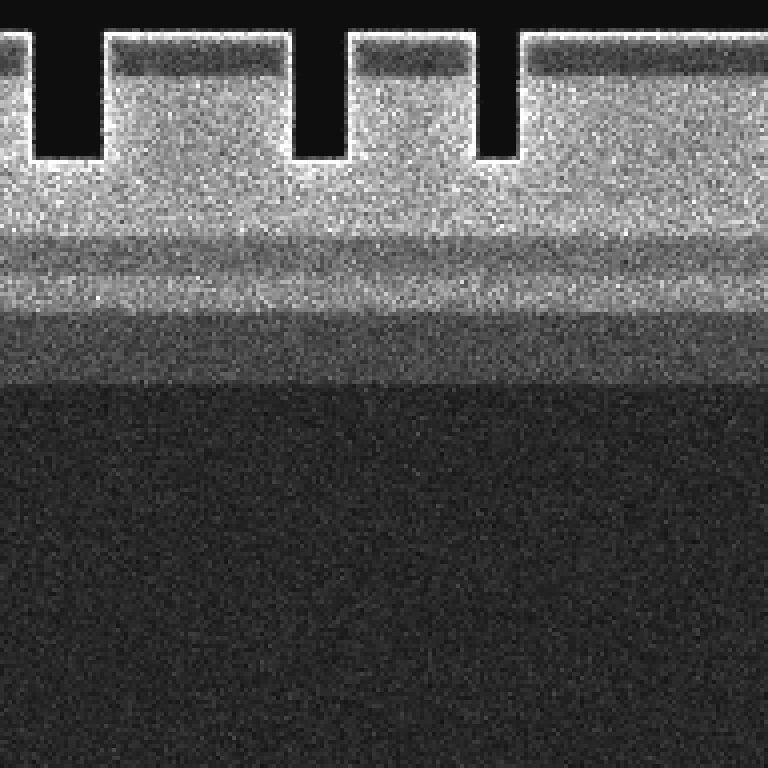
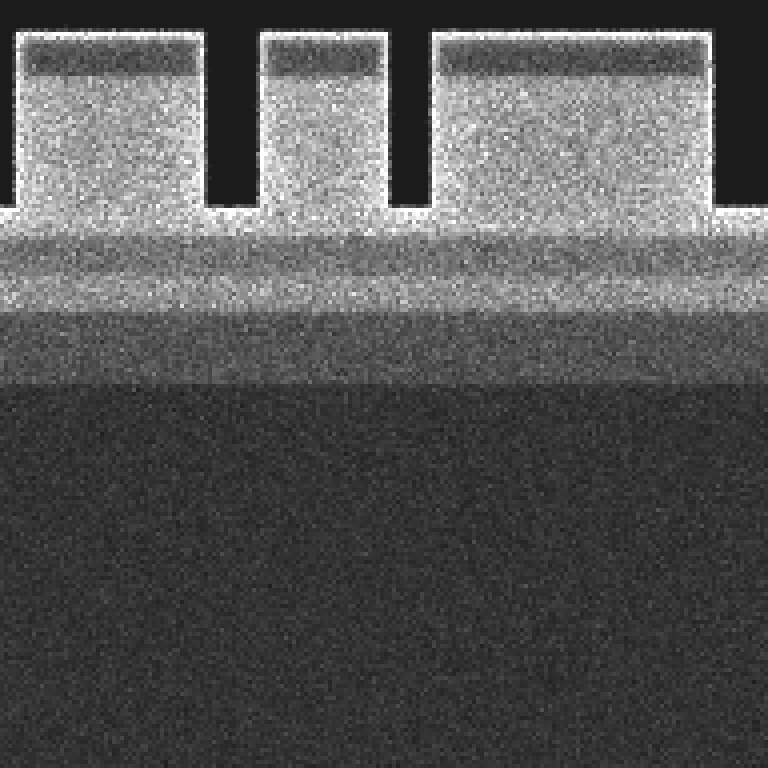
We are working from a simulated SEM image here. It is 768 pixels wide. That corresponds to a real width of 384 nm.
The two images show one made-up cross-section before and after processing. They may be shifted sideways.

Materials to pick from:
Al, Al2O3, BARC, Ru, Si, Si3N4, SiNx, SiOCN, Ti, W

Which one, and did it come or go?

W - removed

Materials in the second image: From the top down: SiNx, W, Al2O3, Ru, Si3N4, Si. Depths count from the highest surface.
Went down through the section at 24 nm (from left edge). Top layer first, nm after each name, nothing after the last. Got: SiNx 22, W 80, Al2O3 20, Ru 18, Si3N4 36, Si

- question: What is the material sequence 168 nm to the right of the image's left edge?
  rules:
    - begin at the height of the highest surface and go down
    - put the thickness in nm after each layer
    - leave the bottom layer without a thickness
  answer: SiNx 22, W 80, Al2O3 20, Ru 18, Si3N4 36, Si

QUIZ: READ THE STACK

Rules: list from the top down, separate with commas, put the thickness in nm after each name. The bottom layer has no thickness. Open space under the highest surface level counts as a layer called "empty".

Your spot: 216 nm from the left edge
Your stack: SiNx 22, W 80, Al2O3 20, Ru 18, Si3N4 36, Si